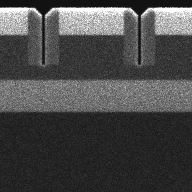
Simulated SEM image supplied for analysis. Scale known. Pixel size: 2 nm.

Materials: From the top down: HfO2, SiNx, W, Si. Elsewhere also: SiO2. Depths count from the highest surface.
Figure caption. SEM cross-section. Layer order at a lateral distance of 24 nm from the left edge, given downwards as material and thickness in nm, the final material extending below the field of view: HfO2 54, SiNx 90, W 64, Si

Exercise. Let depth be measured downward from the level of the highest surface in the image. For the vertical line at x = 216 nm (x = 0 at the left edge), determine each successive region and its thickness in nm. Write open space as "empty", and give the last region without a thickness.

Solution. HfO2 54, SiNx 90, W 64, Si